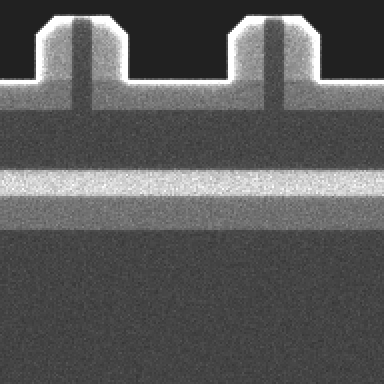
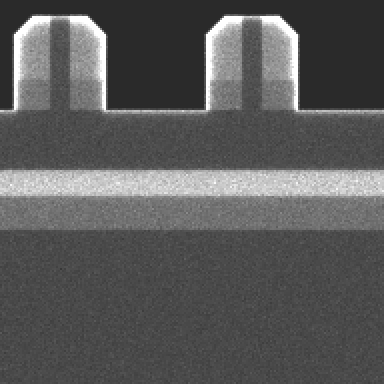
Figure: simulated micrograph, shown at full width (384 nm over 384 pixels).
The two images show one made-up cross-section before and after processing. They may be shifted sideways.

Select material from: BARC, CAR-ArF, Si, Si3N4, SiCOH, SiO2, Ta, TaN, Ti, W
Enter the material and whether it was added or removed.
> Si3N4 / removed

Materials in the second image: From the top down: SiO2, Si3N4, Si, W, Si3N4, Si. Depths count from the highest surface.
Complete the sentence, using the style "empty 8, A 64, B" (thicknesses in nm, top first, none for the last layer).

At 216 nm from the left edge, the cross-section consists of empty 8, SiO2 56, Si3N4 30, Si 60, W 26, Si3N4 34, Si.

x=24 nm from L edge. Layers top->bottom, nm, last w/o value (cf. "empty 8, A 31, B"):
empty 8, SiO2 56, Si3N4 30, Si 60, W 26, Si3N4 34, Si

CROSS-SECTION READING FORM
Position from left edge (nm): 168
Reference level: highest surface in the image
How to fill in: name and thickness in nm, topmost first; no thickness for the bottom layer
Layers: empty 94, Si 60, W 26, Si3N4 34, Si